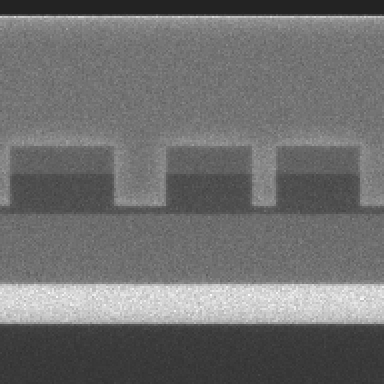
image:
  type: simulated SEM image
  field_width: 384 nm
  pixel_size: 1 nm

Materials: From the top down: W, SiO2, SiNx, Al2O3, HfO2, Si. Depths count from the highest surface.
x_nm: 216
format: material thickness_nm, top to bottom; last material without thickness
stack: W 130, SiO2 28, SiNx 40, Al2O3 70, HfO2 40, Si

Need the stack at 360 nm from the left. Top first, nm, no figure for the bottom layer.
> W 190, SiNx 8, Al2O3 70, HfO2 40, Si